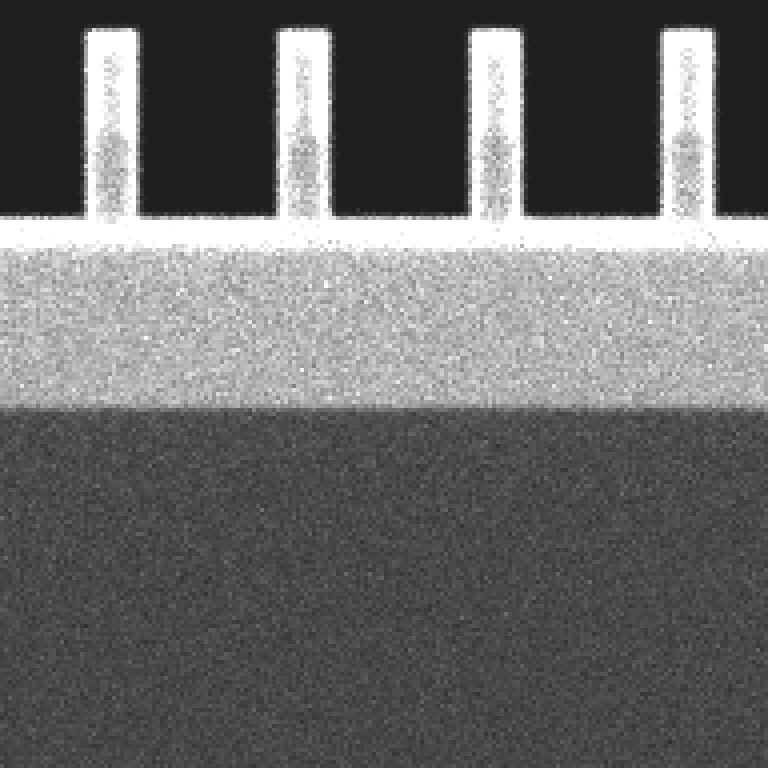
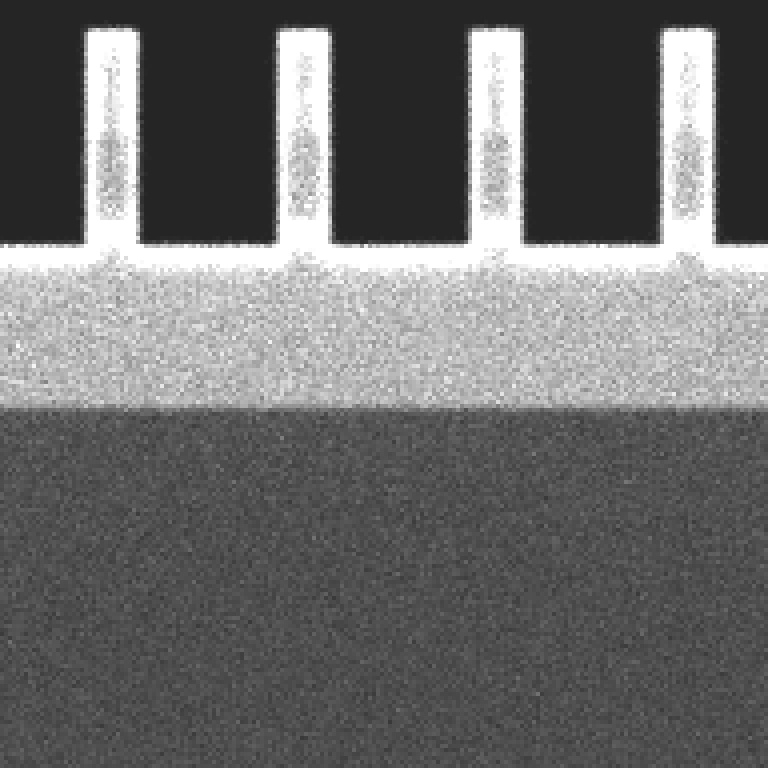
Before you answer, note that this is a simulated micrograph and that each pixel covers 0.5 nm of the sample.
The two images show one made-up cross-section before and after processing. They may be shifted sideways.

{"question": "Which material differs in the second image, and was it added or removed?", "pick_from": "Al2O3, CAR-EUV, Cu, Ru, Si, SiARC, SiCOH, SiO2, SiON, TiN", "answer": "Ru, removed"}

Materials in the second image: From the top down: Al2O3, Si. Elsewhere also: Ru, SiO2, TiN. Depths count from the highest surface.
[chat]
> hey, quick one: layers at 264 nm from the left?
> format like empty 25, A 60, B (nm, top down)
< empty 108, Al2O3 80, Si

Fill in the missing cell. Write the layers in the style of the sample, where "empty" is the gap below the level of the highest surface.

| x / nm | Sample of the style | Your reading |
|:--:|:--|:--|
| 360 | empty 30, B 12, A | empty 108, Al2O3 80, Si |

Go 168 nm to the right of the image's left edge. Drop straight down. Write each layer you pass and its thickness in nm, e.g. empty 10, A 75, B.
empty 108, Al2O3 80, Si